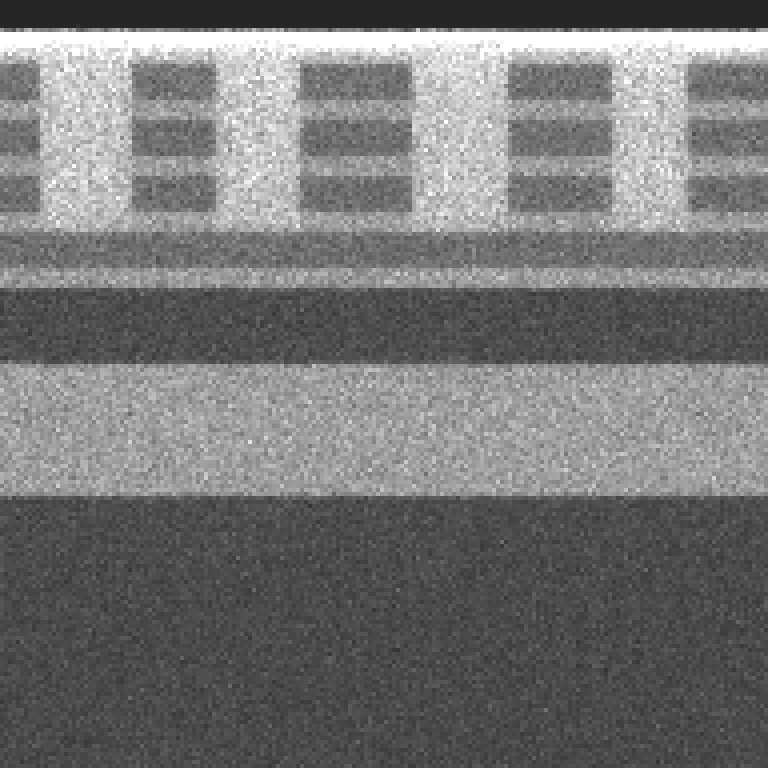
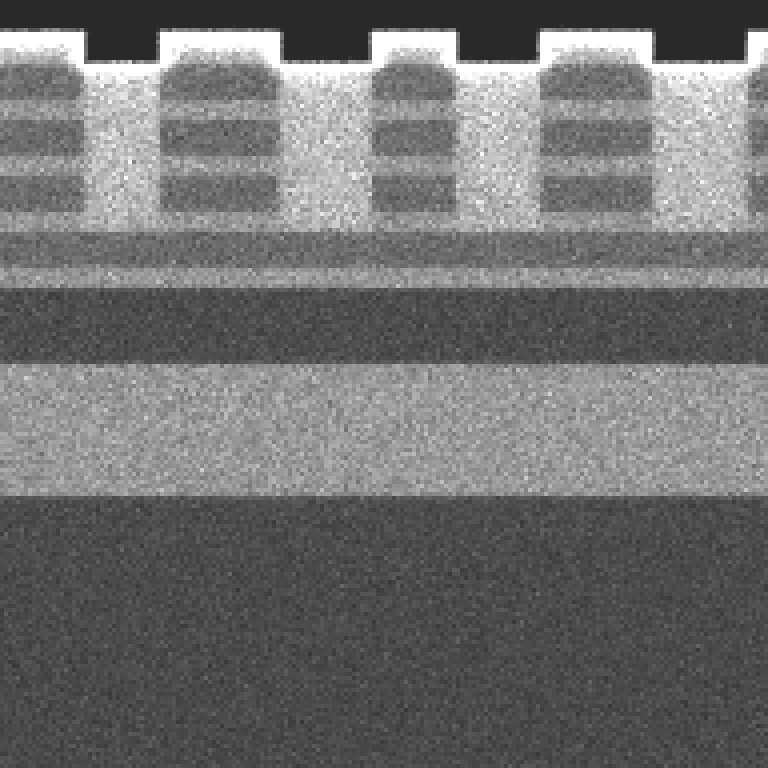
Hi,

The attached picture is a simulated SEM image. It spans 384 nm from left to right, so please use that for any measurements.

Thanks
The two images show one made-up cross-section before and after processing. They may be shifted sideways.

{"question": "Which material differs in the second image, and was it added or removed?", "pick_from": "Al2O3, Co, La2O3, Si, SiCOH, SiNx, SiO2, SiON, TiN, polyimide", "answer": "Co, removed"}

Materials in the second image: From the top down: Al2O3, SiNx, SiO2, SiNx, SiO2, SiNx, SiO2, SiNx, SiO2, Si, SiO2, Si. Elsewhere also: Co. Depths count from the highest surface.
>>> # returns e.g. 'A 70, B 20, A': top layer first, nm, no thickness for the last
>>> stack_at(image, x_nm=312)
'Al2O3 16, SiNx 18, SiO2 10, SiNx 18, SiO2 10, SiNx 18, SiO2 10, SiNx 18, SiO2 10, Si 38, SiO2 66, Si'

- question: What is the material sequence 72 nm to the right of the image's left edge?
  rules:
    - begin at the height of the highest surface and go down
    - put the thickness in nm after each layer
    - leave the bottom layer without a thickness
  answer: empty 16, Co 84, SiNx 18, SiO2 10, Si 38, SiO2 66, Si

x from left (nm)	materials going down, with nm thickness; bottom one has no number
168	empty 16, Co 84, SiNx 18, SiO2 10, Si 38, SiO2 66, Si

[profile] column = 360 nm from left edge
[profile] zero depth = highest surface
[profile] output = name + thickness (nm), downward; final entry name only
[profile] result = empty 16, Co 84, SiNx 18, SiO2 10, Si 38, SiO2 66, Si